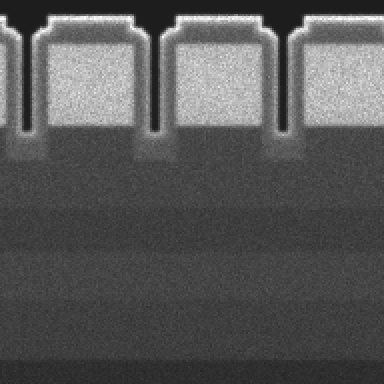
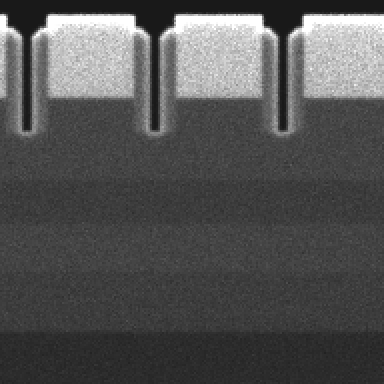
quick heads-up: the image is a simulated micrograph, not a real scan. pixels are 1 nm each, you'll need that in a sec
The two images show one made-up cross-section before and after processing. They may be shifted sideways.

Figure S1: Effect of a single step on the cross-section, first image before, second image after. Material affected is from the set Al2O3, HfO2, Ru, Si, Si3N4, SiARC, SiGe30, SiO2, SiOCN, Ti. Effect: removed SiO2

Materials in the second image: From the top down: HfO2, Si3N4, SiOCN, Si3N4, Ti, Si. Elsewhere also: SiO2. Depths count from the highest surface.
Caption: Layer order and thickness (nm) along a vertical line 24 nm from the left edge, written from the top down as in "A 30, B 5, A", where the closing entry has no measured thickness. empty 116, Si3N4 48, SiOCN 44, Si3N4 48, Ti 60, Si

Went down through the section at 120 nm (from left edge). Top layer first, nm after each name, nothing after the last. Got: HfO2 82, Si3N4 82, SiOCN 44, Si3N4 48, Ti 60, Si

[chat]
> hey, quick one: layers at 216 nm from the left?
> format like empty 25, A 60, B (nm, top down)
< HfO2 82, Si3N4 82, SiOCN 44, Si3N4 48, Ti 60, Si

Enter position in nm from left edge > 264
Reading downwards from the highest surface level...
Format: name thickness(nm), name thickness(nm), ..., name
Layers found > empty 12, SiO2 104, Si3N4 48, SiOCN 44, Si3N4 48, Ti 60, Si